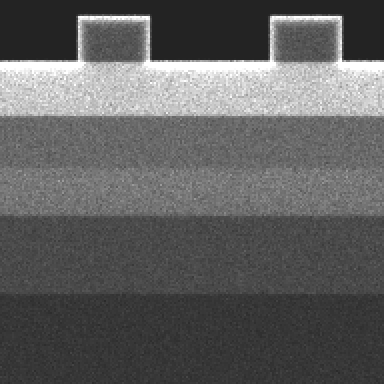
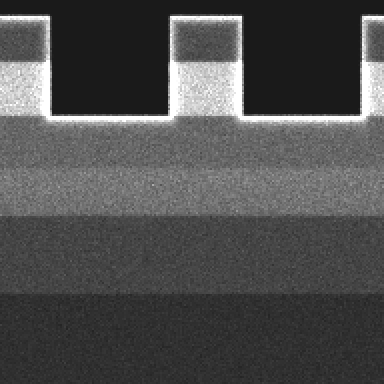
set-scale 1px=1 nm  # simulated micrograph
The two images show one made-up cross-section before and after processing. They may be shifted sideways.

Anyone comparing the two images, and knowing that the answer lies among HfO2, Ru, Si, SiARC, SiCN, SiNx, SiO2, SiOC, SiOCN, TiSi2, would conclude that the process removed HfO2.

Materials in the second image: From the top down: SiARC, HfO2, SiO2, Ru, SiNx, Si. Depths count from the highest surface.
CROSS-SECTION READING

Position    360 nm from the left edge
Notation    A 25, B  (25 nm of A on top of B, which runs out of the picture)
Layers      empty 100, SiO2 52, Ru 48, SiNx 78, Si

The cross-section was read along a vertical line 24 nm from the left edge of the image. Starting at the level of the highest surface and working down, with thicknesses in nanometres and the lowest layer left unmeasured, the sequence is SiARC 46, HfO2 54, SiO2 52, Ru 48, SiNx 78, Si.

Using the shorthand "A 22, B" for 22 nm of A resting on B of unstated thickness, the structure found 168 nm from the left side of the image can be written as empty 100, SiO2 52, Ru 48, SiNx 78, Si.